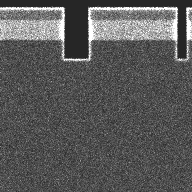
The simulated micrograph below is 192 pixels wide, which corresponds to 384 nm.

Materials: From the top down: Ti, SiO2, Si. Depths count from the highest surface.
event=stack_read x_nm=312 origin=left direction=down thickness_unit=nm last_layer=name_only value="Ti 24, SiO2 40, Si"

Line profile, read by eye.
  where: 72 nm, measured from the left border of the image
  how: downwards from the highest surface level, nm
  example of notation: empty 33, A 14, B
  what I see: Ti 24, SiO2 40, Si